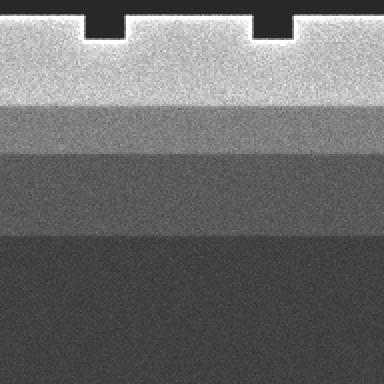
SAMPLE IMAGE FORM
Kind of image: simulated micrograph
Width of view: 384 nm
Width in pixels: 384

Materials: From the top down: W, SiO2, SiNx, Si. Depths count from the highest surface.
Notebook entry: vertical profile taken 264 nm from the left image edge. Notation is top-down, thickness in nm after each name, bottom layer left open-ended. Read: empty 24, W 66, SiO2 48, SiNx 82, Si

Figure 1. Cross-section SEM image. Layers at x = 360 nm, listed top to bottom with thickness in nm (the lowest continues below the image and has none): W 90, SiO2 48, SiNx 82, Si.